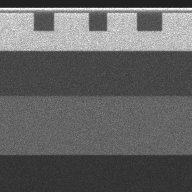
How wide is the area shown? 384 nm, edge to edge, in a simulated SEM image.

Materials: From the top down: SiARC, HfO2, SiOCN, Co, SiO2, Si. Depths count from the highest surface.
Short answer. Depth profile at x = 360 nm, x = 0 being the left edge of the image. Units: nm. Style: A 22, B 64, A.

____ SiARC 10, HfO2 76, SiOCN 90, Co 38, SiO2 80, Si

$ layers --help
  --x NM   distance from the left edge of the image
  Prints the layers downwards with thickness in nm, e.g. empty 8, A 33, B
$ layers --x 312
SiARC 46, HfO2 40, SiOCN 90, Co 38, SiO2 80, Si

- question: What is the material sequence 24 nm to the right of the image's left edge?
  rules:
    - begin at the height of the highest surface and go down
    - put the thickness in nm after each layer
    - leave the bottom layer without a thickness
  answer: SiARC 10, HfO2 76, SiOCN 90, Co 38, SiO2 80, Si